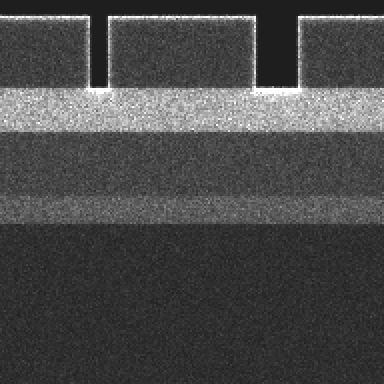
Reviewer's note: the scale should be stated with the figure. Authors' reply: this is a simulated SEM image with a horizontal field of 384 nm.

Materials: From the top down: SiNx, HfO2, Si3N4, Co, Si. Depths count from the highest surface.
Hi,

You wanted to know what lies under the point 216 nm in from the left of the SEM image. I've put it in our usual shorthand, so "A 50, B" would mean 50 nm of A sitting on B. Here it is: SiNx 72, HfO2 44, Si3N4 64, Co 28, Si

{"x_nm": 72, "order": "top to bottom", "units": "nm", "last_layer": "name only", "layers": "SiNx 72, HfO2 44, Si3N4 64, Co 28, Si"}